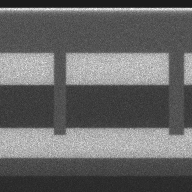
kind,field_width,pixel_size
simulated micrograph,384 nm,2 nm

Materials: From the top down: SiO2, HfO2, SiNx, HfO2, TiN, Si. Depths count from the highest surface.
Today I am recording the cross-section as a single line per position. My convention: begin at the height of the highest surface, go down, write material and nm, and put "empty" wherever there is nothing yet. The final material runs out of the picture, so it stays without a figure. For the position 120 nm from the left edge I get SiO2 254, HfO2 46, TiN 36, Si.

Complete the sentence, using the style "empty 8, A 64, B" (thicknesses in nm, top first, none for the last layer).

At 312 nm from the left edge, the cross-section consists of SiO2 90, HfO2 64, SiNx 86, HfO2 60, TiN 36, Si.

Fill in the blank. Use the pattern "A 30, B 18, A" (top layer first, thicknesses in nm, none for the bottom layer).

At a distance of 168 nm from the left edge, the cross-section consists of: SiO2 90, HfO2 64, SiNx 86, HfO2 60, TiN 36, Si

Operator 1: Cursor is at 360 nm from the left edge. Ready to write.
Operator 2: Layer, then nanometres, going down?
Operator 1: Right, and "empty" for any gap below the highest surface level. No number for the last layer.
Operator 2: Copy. SiO2 254, HfO2 46, TiN 36, Si